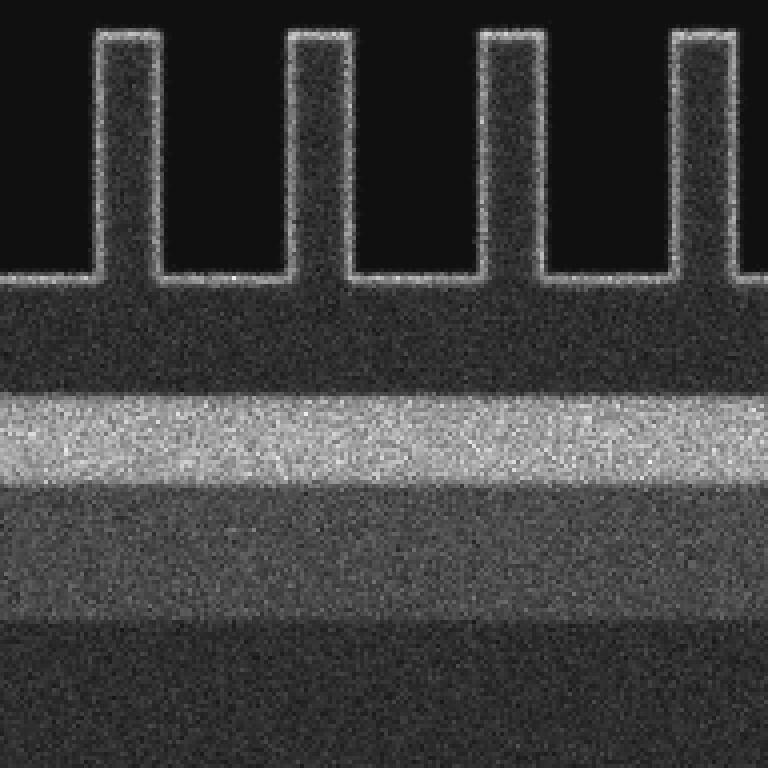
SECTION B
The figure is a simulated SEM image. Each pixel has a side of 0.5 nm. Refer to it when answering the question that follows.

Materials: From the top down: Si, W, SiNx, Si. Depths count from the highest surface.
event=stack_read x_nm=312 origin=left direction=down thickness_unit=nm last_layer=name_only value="empty 122, Si 60, W 44, SiNx 68, Si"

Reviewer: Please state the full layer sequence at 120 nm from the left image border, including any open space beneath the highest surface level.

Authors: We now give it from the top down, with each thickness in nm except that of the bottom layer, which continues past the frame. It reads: empty 122, Si 60, W 44, SiNx 68, Si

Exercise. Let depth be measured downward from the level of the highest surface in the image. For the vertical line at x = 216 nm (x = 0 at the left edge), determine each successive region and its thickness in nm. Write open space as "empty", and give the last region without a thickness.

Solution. empty 122, Si 60, W 44, SiNx 68, Si